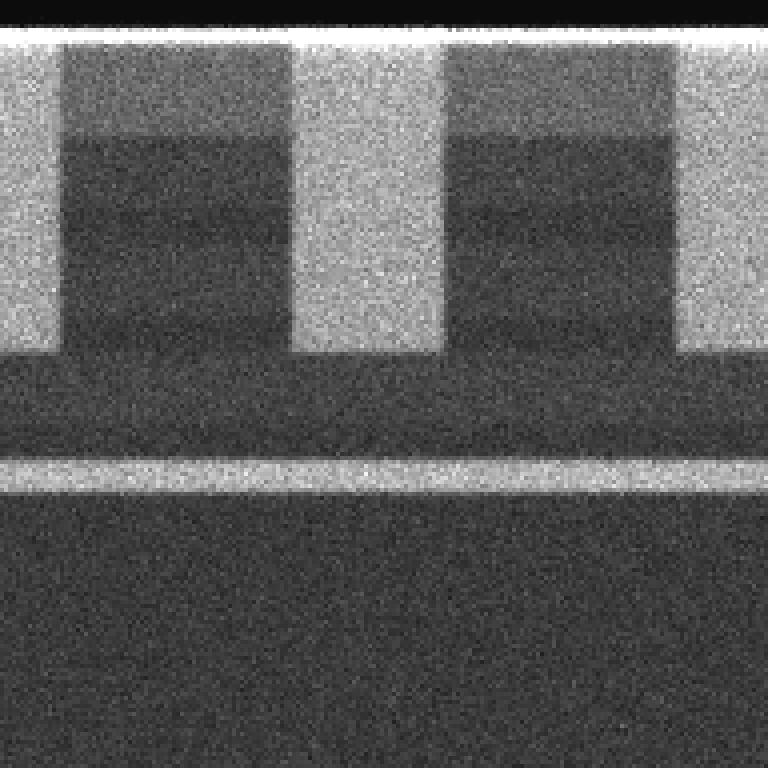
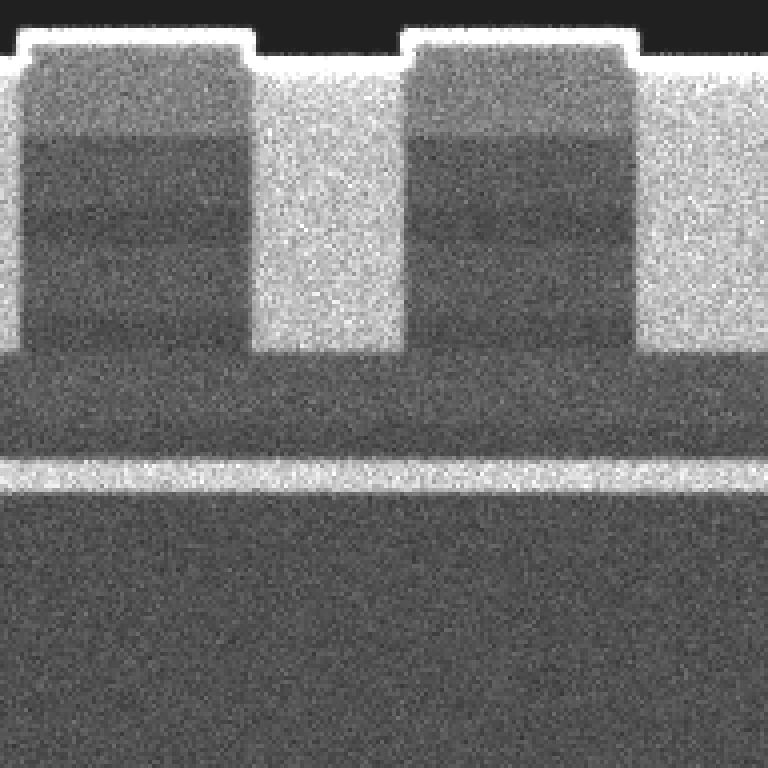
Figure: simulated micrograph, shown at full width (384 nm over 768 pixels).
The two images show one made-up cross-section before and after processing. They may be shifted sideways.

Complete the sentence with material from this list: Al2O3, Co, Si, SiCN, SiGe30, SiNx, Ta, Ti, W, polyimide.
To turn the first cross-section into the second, Co must be removed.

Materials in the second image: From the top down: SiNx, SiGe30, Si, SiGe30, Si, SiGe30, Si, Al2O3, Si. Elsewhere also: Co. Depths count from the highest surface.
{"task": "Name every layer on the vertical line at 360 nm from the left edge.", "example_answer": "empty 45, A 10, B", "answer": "empty 14, Co 146, SiGe30 36, Si 18, Al2O3 16, Si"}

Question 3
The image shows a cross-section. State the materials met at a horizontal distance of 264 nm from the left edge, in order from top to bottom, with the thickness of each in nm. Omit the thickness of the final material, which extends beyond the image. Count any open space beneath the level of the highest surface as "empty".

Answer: SiNx 52, SiGe30 36, Si 18, SiGe30 36, Si 18, SiGe30 36, Si 18, Al2O3 16, Si